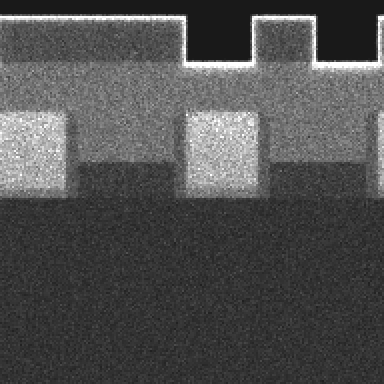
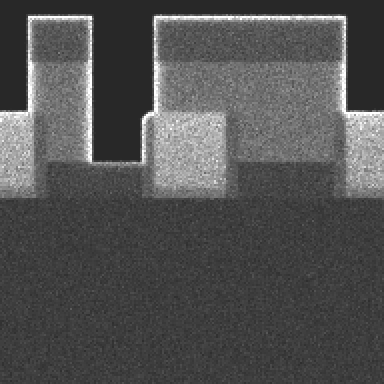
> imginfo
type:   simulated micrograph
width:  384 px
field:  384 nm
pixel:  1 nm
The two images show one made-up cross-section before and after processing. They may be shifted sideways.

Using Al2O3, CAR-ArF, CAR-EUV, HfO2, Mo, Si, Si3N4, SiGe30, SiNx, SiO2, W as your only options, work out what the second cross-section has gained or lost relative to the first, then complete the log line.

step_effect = removed SiO2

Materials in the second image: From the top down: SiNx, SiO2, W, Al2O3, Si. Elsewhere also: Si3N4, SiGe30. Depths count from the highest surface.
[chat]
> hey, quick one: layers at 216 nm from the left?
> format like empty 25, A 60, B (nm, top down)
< SiNx 46, SiO2 50, W 76, Al2O3 10, Si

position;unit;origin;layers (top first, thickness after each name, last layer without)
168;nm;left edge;SiNx 46, SiO2 50, W 76, Al2O3 10, Si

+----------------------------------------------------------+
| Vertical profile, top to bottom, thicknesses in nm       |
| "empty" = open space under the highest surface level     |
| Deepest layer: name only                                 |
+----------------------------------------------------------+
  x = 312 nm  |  SiNx 46, SiO2 100, SiGe30 36, Si